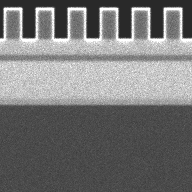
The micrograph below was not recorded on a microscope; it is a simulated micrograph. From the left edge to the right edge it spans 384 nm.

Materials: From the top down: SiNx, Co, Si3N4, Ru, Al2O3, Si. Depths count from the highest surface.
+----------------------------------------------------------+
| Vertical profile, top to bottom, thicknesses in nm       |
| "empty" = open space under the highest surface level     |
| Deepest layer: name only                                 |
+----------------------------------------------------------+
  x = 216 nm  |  SiNx 62, Co 32, Si3N4 12, Ru 76, Al2O3 12, Si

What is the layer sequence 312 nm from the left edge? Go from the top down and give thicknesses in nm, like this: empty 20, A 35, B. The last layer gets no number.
empty 62, Co 32, Si3N4 12, Ru 76, Al2O3 12, Si